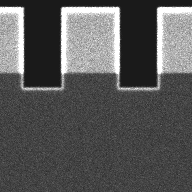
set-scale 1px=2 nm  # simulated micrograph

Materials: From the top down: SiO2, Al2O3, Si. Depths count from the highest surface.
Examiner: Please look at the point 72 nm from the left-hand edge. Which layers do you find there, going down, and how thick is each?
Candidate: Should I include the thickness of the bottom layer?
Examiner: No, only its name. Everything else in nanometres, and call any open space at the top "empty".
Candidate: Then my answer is empty 160, Si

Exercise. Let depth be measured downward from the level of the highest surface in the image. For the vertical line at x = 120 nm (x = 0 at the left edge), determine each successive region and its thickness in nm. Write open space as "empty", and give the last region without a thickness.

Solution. empty 160, Si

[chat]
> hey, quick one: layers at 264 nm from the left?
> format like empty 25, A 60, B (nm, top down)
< empty 160, Si